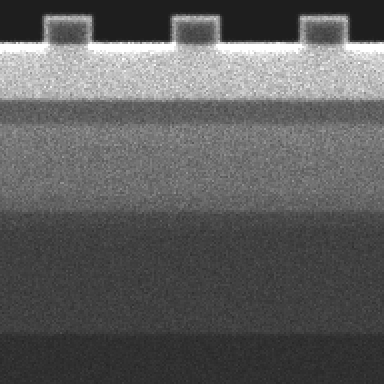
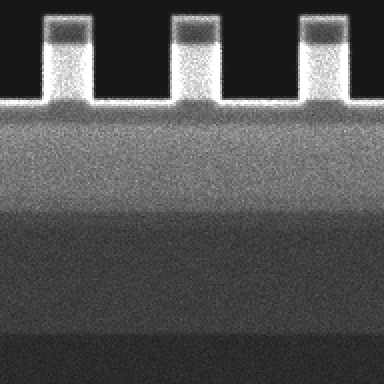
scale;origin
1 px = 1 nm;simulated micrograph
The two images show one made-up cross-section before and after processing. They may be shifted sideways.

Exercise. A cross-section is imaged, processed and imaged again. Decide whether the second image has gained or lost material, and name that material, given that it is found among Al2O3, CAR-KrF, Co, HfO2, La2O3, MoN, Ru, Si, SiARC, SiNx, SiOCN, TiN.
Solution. removed: HfO2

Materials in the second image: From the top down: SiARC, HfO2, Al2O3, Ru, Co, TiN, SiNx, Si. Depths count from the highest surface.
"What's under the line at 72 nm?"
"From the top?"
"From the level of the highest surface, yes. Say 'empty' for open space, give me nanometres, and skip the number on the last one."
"SiARC 28, HfO2 56, Al2O3 24, Ru 72, Co 16, TiN 16, SiNx 106, Si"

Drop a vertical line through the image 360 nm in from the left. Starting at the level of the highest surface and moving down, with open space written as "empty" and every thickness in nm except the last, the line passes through empty 84, Al2O3 24, Ru 72, Co 16, TiN 16, SiNx 106, Si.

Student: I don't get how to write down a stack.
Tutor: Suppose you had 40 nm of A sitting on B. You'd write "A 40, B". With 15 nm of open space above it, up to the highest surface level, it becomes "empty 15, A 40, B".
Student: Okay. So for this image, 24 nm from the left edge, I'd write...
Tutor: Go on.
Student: empty 84, Al2O3 24, Ru 72, Co 16, TiN 16, SiNx 106, Si